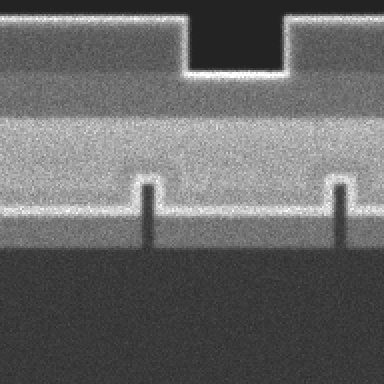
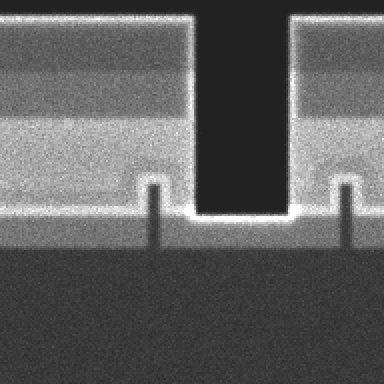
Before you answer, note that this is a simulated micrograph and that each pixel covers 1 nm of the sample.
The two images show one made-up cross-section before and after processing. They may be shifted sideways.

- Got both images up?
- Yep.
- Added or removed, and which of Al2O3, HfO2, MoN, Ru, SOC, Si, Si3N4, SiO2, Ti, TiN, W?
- removed, HfO2 and Ru and SiO2 and W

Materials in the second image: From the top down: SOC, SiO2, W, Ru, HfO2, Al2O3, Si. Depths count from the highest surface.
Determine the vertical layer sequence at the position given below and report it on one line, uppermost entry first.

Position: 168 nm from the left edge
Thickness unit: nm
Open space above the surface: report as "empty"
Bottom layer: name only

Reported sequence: SOC 56, SiO2 46, W 40, Ru 20, HfO2 38, Al2O3 32, Si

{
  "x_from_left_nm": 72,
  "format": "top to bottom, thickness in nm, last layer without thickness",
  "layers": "SOC 56, SiO2 46, W 72, Ru 16, HfO2 10, Al2O3 32, Si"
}